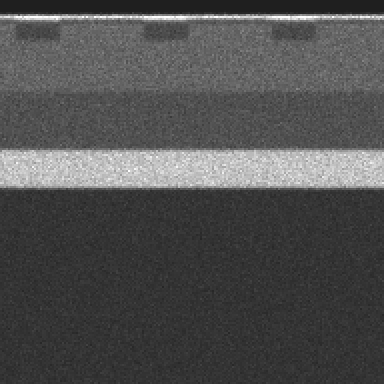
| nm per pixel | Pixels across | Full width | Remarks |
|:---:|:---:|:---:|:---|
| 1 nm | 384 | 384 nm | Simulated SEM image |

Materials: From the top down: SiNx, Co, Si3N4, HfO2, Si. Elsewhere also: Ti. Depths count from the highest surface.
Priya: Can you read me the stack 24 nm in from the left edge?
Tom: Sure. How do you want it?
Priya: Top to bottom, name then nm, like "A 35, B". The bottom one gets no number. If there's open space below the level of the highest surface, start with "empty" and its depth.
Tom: SiNx 24, Co 52, Si3N4 58, HfO2 38, Si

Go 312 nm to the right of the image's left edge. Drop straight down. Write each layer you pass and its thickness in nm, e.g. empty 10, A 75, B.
SiNx 24, Co 52, Si3N4 58, HfO2 38, Si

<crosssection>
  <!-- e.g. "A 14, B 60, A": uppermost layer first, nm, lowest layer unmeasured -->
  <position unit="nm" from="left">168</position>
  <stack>SiNx 24, Co 52, Si3N4 58, HfO2 38, Si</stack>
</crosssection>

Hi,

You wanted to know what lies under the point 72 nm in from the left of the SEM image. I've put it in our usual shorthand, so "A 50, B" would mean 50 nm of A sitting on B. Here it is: Ti 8, Co 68, Si3N4 58, HfO2 38, Si